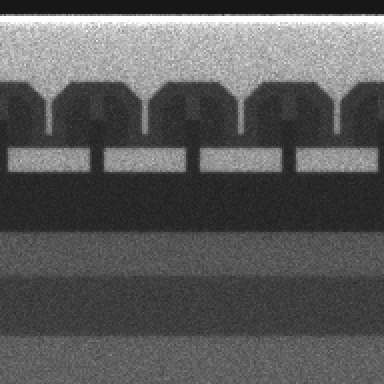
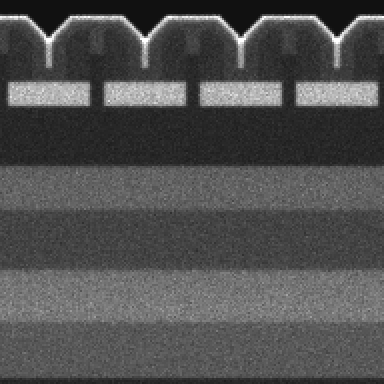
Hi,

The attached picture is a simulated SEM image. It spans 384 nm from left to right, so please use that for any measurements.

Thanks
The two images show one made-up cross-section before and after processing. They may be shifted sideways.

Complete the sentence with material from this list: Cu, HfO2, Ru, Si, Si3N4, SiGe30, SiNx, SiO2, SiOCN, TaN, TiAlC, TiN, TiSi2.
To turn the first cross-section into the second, HfO2 must be removed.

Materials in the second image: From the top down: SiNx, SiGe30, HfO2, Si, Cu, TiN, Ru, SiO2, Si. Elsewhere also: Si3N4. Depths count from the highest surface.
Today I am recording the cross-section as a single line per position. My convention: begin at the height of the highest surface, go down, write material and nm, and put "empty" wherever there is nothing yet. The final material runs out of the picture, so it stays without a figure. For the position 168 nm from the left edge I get SiNx 20, SiGe30 46, HfO2 24, Si 60, Cu 44, TiN 60, Ru 52, SiO2 56, Si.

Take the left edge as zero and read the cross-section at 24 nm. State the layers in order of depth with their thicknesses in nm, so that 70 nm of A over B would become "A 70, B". SiNx 20, SiGe30 46, HfO2 24, Si 60, Cu 44, TiN 60, Ru 52, SiO2 56, Si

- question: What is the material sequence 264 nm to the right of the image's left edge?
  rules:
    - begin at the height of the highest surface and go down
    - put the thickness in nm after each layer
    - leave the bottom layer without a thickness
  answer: SiNx 20, SiGe30 46, HfO2 24, Si 60, Cu 44, TiN 60, Ru 52, SiO2 56, Si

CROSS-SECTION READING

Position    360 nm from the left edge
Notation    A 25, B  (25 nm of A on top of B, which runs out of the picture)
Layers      SiNx 20, SiGe30 46, HfO2 24, Si 60, Cu 44, TiN 60, Ru 52, SiO2 56, Si